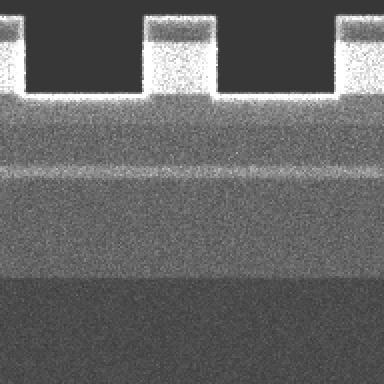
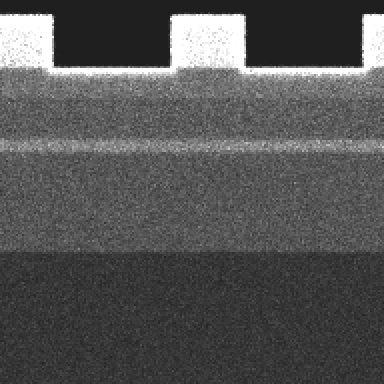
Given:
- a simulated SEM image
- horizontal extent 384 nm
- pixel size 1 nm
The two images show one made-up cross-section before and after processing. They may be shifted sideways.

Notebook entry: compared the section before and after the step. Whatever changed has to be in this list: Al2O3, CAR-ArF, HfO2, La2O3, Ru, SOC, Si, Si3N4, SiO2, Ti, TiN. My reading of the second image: SOC removed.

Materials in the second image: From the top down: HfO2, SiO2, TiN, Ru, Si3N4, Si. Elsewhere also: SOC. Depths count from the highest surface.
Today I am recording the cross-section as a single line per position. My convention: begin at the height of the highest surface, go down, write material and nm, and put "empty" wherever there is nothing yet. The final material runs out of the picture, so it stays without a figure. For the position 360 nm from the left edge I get empty 52, SiO2 30, TiN 42, Ru 12, Si3N4 100, Si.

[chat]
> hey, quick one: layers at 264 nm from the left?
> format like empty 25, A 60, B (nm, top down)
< empty 52, SiO2 30, TiN 42, Ru 12, Si3N4 100, Si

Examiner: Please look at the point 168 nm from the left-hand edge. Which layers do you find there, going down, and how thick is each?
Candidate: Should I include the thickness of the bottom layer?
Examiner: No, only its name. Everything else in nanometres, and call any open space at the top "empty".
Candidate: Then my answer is empty 52, SiO2 30, TiN 42, Ru 12, Si3N4 100, Si